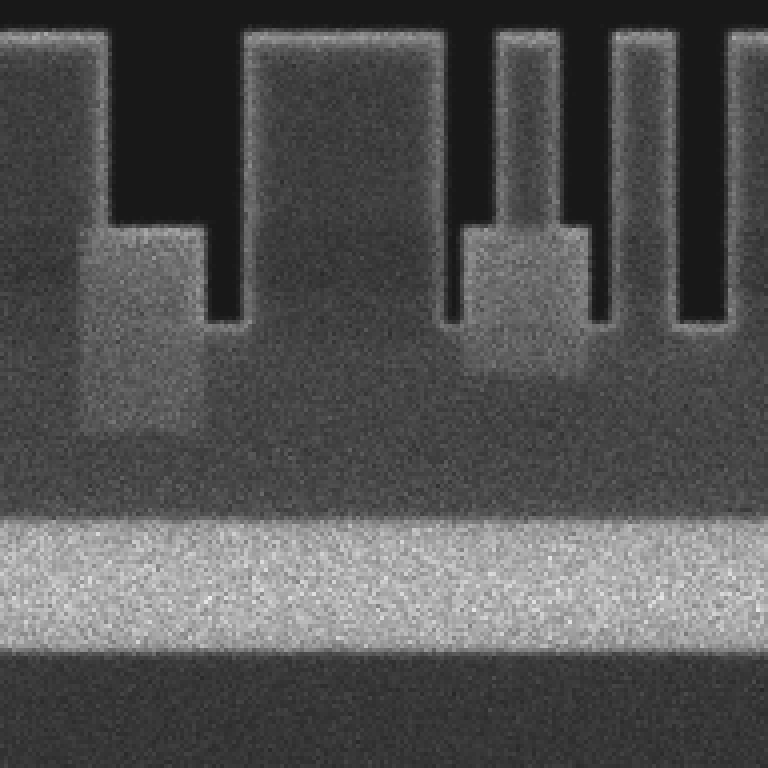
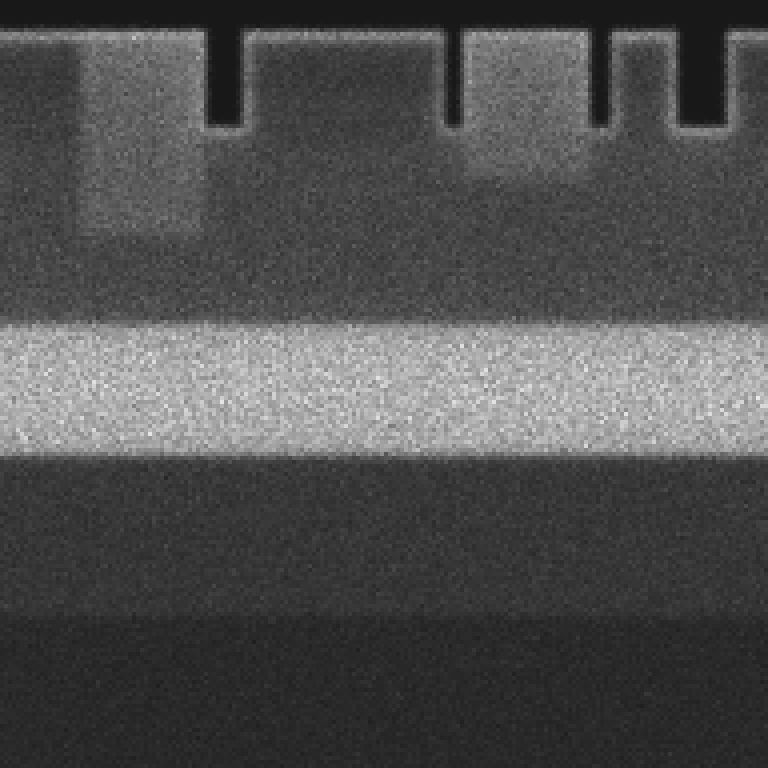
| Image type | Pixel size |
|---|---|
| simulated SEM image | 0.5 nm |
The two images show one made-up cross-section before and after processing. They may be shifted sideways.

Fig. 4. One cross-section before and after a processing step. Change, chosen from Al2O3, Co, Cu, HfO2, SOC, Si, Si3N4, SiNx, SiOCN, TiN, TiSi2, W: SOC removed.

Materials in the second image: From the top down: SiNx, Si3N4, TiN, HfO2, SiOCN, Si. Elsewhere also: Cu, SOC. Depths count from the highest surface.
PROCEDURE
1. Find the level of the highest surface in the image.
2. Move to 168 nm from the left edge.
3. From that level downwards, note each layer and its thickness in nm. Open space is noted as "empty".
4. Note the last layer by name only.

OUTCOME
SiNx 32, Si3N4 24, TiN 90, HfO2 66, SiOCN 80, Si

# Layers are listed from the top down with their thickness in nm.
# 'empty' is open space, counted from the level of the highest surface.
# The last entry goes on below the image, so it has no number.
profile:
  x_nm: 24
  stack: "SiNx 32, Si3N4 24, TiN 90, HfO2 66, SiOCN 80, Si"